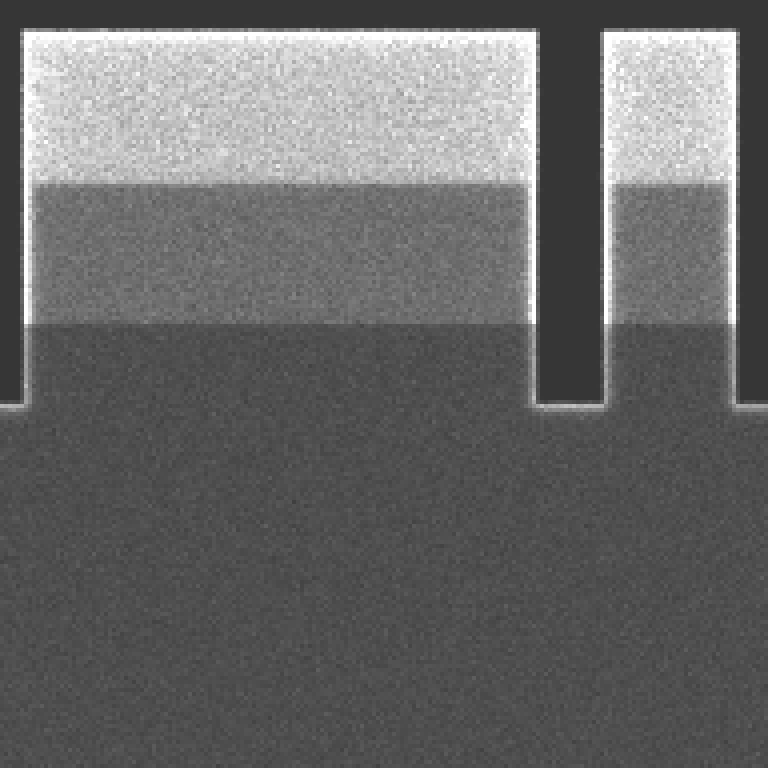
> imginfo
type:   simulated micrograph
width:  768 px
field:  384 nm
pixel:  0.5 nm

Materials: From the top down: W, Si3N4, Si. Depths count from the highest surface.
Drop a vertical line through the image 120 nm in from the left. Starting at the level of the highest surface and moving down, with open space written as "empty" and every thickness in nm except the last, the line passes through W 76, Si3N4 70, Si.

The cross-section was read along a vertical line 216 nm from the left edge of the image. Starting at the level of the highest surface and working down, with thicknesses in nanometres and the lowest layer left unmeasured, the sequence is W 76, Si3N4 70, Si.